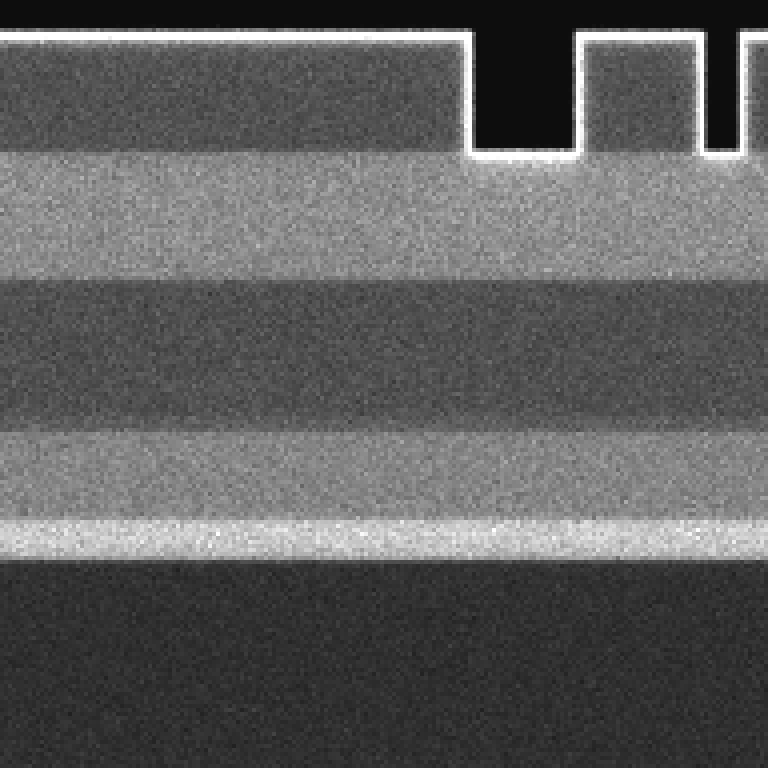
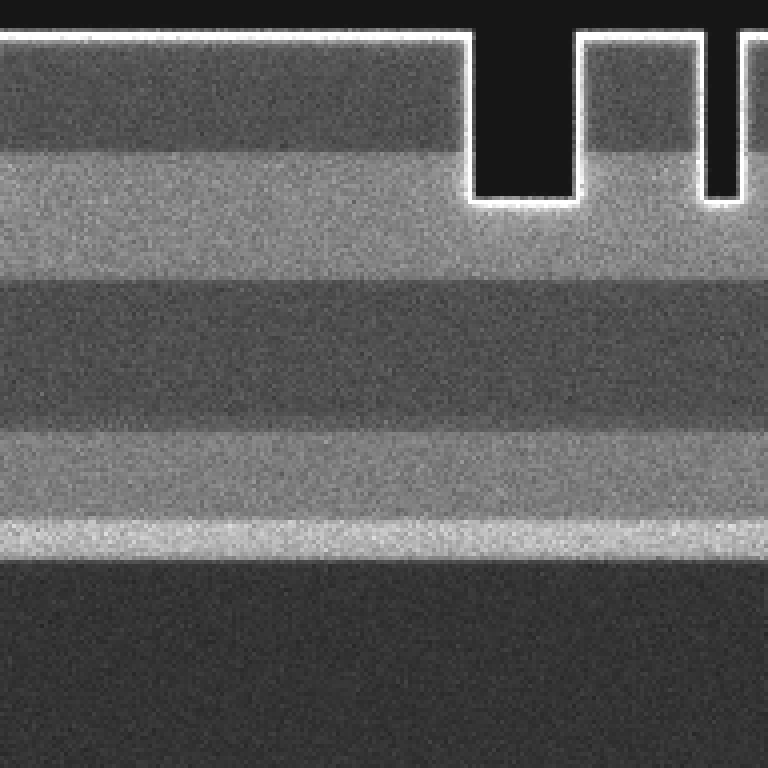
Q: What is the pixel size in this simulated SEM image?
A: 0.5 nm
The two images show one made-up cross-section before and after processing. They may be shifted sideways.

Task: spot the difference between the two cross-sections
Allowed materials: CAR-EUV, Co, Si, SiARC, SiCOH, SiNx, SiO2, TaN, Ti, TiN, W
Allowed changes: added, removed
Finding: removed Co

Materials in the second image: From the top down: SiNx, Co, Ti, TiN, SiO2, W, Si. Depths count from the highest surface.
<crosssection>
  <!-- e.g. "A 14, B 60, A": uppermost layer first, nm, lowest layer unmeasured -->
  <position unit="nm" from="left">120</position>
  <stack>SiNx 60, Co 64, Ti 68, TiN 8, SiO2 44, W 20, Si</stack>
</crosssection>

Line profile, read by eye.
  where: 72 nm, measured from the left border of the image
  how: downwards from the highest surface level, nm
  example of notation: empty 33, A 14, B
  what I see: SiNx 60, Co 64, Ti 68, TiN 8, SiO2 44, W 20, Si